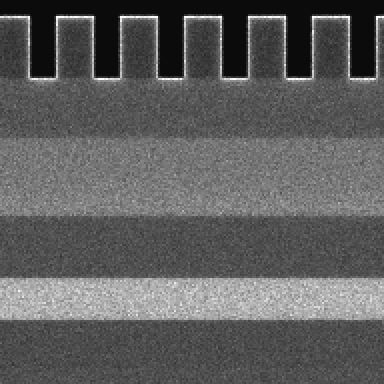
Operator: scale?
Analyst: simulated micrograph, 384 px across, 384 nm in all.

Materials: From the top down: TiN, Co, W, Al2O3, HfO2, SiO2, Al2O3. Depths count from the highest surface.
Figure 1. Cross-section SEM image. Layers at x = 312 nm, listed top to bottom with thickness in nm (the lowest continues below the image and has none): TiN 62, Co 60, W 78, Al2O3 62, HfO2 42, SiO2 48, Al2O3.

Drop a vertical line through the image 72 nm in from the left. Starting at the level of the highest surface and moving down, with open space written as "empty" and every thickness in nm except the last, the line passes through TiN 62, Co 60, W 78, Al2O3 62, HfO2 42, SiO2 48, Al2O3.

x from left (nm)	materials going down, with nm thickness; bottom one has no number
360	empty 62, Co 60, W 78, Al2O3 62, HfO2 42, SiO2 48, Al2O3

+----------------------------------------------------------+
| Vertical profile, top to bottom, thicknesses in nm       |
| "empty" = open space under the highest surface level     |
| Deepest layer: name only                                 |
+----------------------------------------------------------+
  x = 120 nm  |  TiN 62, Co 60, W 78, Al2O3 62, HfO2 42, SiO2 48, Al2O3